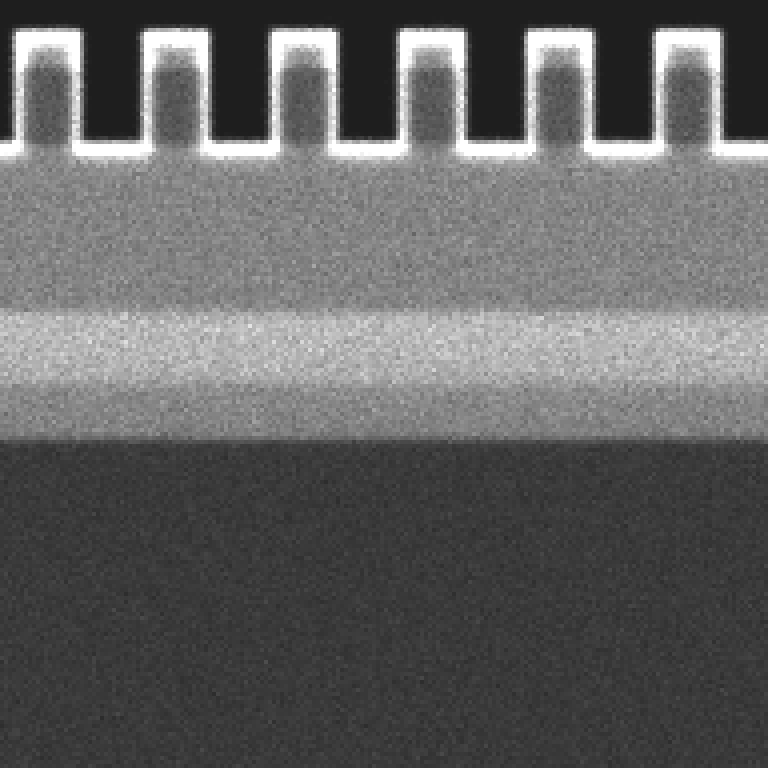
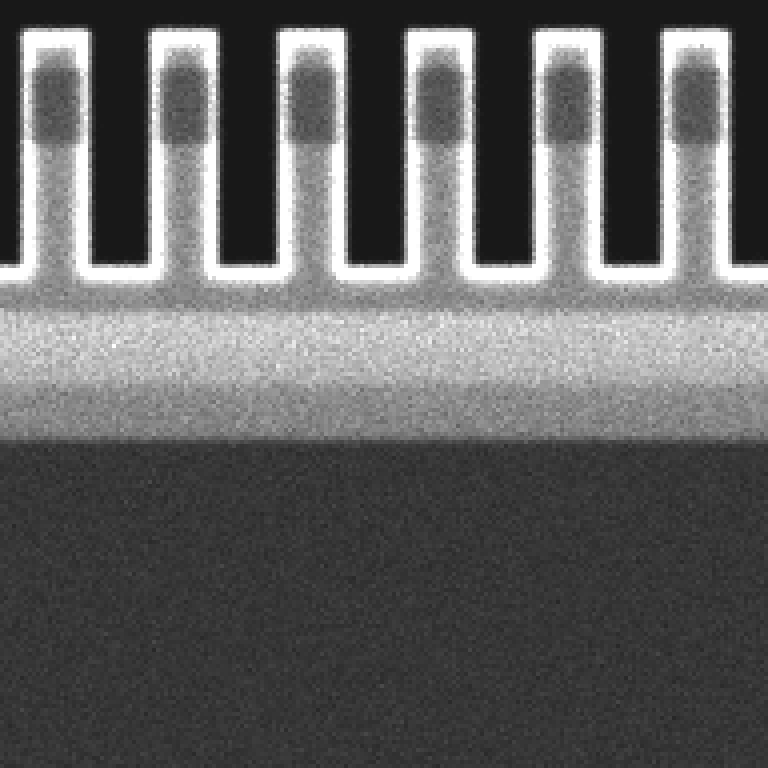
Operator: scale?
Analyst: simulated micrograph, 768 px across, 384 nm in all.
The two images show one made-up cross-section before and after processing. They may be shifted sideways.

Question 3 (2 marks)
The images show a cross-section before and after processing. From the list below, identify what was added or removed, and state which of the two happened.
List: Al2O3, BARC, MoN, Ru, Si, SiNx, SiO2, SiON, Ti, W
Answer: Al2O3 was removed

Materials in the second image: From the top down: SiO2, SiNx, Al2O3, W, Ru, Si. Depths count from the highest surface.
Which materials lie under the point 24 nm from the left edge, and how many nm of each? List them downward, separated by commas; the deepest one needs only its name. SiO2 18, SiNx 38, Al2O3 84, W 36, Ru 28, Si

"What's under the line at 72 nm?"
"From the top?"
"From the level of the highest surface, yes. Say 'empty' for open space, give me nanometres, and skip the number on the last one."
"empty 118, Al2O3 22, W 36, Ru 28, Si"